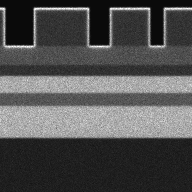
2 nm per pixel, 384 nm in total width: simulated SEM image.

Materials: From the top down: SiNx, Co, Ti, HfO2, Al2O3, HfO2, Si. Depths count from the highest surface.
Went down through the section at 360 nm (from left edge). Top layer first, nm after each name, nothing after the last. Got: SiNx 76, Co 38, Ti 22, HfO2 34, Al2O3 26, HfO2 64, Si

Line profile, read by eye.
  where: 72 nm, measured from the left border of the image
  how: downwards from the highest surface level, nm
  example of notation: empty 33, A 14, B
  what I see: SiNx 76, Co 38, Ti 22, HfO2 34, Al2O3 26, HfO2 64, Si